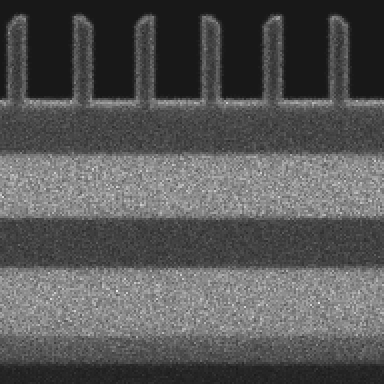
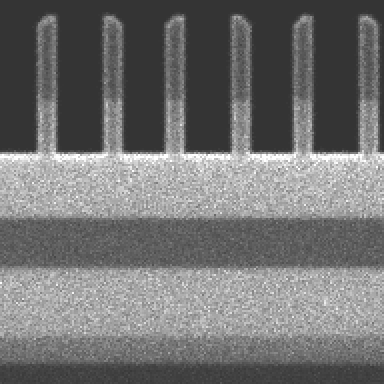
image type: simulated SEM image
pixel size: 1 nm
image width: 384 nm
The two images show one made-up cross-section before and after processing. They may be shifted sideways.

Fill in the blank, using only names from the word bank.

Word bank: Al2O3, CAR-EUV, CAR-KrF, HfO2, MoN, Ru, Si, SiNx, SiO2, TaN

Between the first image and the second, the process removed Al2O3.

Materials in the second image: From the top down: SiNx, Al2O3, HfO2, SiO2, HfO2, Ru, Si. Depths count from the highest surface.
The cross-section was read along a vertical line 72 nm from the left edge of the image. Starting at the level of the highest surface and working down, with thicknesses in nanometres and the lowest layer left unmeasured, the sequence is empty 138, HfO2 64, SiO2 50, HfO2 68, Ru 28, Si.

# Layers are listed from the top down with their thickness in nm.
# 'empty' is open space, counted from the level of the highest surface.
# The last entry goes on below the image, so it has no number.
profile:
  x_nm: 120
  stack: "empty 8, SiNx 76, Al2O3 54, HfO2 64, SiO2 50, HfO2 68, Ru 28, Si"